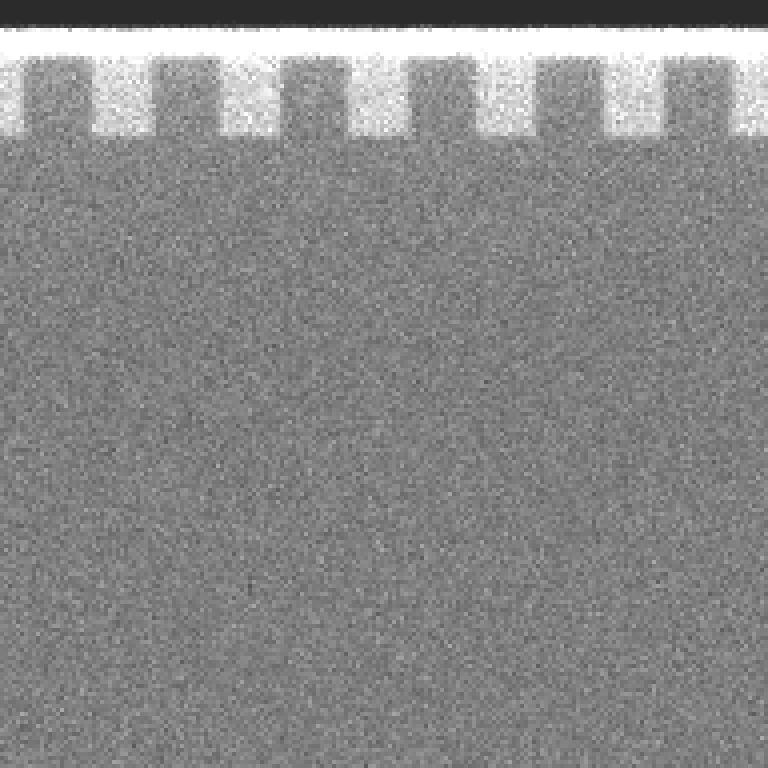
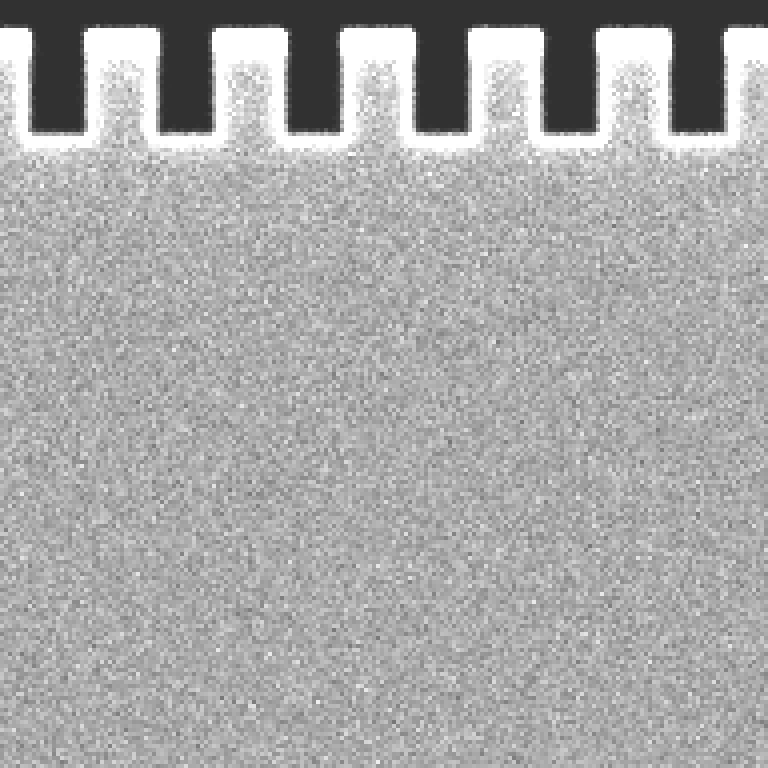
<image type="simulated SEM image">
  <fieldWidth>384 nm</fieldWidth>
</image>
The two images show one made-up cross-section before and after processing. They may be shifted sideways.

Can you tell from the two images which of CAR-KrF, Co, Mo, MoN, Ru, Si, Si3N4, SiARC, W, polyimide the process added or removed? Yes, it removed SiARC.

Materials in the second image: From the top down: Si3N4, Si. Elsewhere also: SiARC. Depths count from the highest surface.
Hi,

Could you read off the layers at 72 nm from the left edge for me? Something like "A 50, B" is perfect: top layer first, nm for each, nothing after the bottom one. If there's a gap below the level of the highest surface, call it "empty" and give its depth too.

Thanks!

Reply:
Si3N4 12, Si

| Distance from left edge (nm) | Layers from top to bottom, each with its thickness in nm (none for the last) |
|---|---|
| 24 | empty 52, Si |